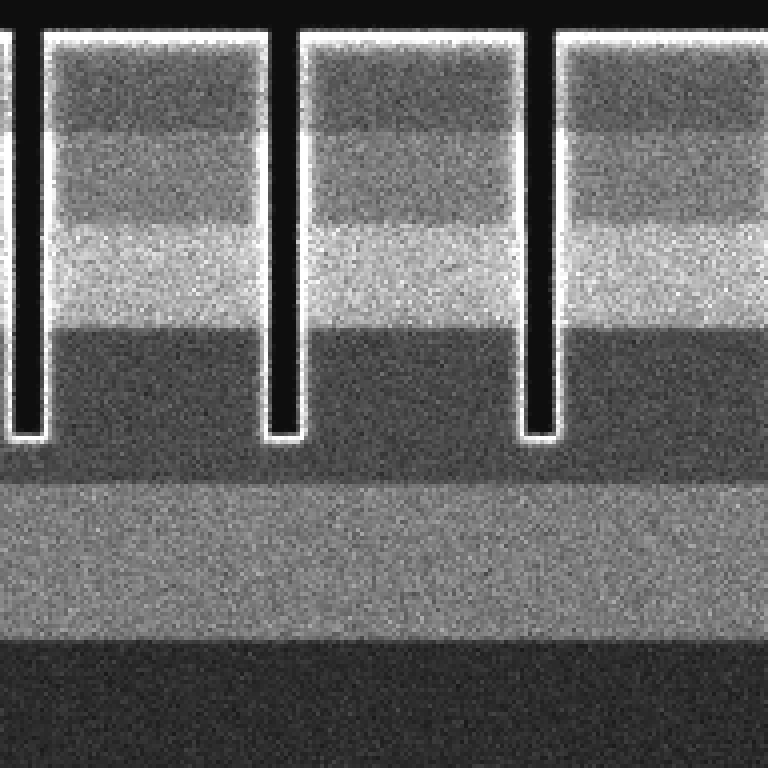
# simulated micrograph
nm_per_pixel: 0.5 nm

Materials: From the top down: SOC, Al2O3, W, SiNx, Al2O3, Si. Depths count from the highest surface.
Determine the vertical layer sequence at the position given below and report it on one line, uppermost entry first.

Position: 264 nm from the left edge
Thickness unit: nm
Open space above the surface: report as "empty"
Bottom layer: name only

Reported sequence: empty 202, SiNx 24, Al2O3 78, Si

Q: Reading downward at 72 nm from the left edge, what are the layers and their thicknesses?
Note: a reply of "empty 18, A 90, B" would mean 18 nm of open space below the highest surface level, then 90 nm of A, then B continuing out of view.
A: SOC 50, Al2O3 46, W 52, SiNx 78, Al2O3 78, Si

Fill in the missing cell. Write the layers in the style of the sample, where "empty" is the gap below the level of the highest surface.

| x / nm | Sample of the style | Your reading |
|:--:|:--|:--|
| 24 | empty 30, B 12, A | SOC 50, Al2O3 46, W 52, SiNx 78, Al2O3 78, Si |